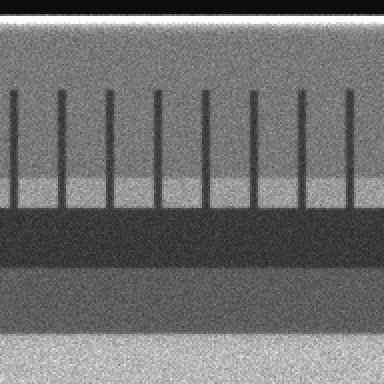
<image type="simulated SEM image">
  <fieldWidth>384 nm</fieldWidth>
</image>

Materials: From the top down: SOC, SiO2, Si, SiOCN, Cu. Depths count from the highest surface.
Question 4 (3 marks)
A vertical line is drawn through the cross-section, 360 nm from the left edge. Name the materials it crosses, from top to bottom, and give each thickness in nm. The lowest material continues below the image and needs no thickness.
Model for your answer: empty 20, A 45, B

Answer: SOC 162, SiO2 30, Si 60, SiOCN 66, Cu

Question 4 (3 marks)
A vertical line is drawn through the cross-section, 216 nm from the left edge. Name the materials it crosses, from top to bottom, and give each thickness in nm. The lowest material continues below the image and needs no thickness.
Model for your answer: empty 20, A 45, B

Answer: SOC 162, SiO2 30, Si 60, SiOCN 66, Cu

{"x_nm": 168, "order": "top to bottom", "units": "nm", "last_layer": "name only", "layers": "SOC 162, SiO2 30, Si 60, SiOCN 66, Cu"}